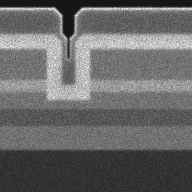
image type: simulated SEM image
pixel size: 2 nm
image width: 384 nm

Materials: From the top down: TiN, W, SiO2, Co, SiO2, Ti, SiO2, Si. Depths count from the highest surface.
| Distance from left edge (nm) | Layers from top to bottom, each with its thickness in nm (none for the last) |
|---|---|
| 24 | TiN 52, W 30, SiO2 62, Co 24, SiO2 34, Ti 34, SiO2 48, Si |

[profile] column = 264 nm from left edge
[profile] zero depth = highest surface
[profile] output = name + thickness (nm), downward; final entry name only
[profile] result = TiN 52, W 30, SiO2 62, Co 24, SiO2 34, Ti 34, SiO2 48, Si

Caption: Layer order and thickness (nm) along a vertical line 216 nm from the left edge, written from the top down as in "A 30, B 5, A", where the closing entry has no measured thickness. TiN 52, W 30, SiO2 62, Co 24, SiO2 34, Ti 34, SiO2 48, Si